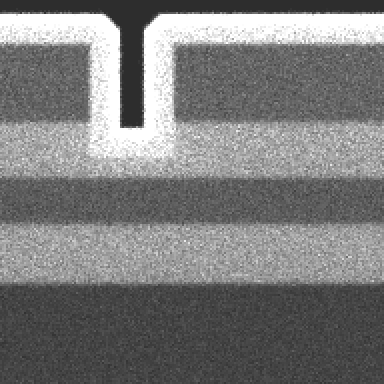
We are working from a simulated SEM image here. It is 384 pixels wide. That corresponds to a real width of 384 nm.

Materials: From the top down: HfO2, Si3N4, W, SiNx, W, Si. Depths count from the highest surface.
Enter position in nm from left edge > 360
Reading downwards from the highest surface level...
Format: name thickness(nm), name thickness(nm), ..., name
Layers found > HfO2 28, Si3N4 78, W 56, SiNx 46, W 60, Si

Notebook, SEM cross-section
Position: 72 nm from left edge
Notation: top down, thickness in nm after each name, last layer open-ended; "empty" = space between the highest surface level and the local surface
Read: HfO2 28, Si3N4 78, W 56, SiNx 46, W 60, Si